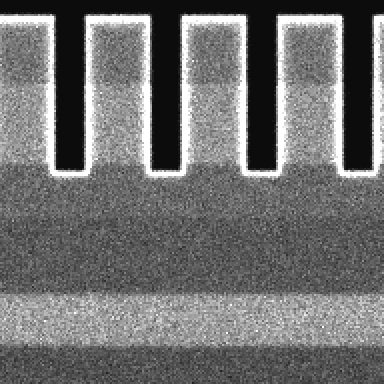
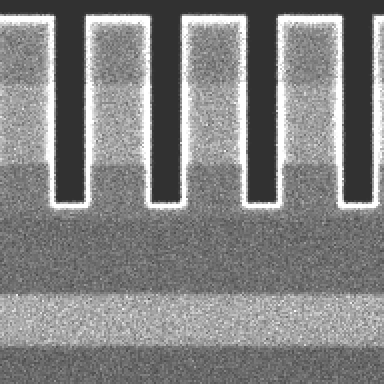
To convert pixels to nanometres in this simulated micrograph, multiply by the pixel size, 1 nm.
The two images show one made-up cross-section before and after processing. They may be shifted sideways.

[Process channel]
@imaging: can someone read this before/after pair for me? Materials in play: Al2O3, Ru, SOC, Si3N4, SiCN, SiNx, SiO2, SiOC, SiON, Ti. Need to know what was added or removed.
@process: Si3N4 removed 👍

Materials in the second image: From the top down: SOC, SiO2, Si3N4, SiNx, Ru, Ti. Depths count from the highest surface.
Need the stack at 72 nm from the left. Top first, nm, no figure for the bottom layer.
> empty 188, Si3N4 14, SiNx 76, Ru 52, Ti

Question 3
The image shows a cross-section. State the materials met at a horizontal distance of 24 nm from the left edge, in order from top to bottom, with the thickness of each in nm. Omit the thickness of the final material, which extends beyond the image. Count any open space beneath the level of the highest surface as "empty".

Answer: SOC 68, SiO2 80, Si3N4 54, SiNx 76, Ru 52, Ti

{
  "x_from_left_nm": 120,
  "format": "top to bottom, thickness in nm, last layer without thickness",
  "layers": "SOC 68, SiO2 80, Si3N4 54, SiNx 76, Ru 52, Ti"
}